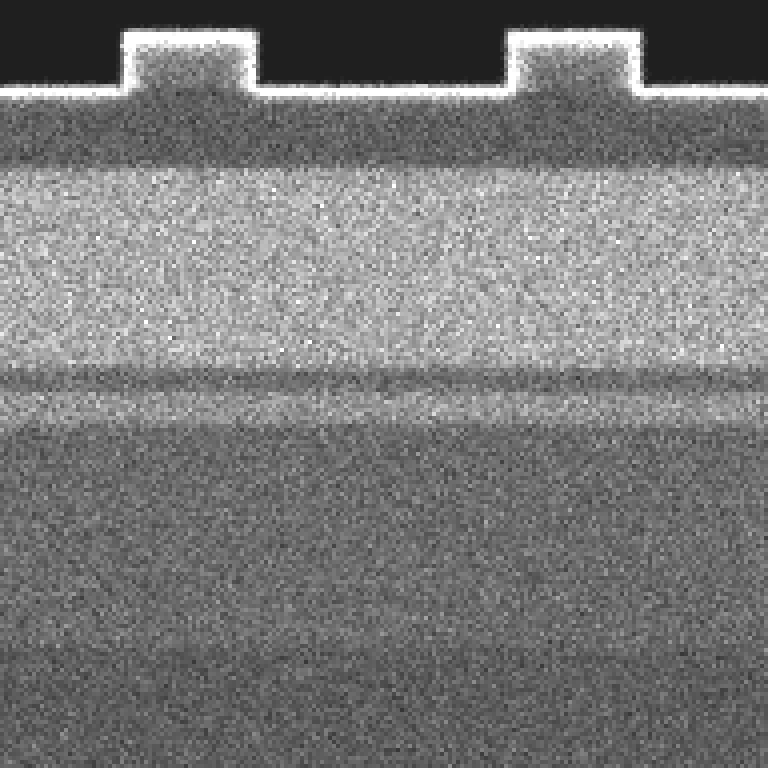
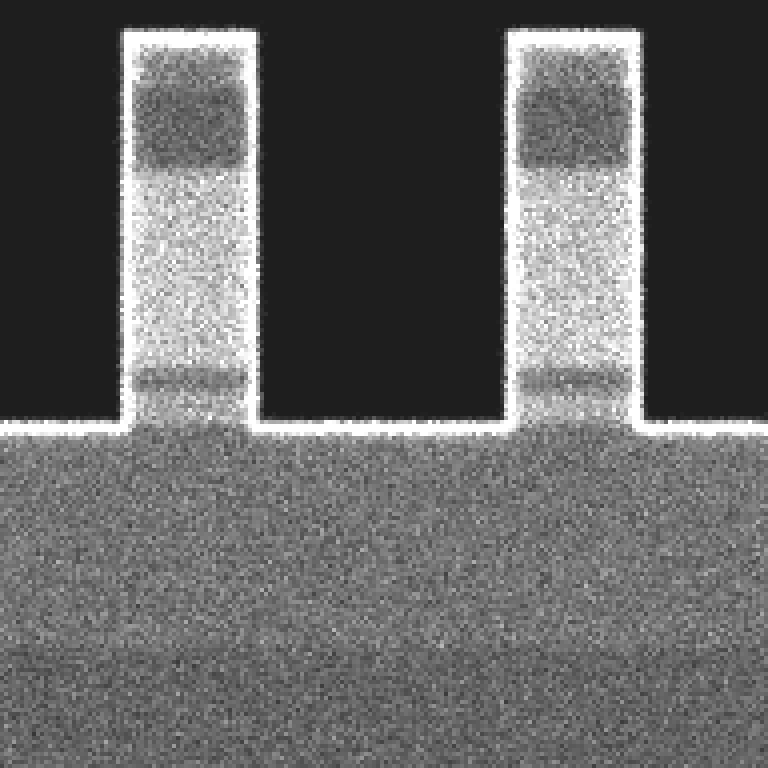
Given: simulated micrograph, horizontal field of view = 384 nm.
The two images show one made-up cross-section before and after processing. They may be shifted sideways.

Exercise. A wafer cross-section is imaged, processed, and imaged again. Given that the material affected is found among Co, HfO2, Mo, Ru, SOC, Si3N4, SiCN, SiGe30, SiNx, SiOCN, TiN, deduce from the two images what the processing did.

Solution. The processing removed Co and Ru and SiNx and TiN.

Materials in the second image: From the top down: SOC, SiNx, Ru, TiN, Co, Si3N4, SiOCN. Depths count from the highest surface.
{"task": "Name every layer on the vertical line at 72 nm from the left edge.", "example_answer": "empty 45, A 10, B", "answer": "SOC 28, SiNx 40, Ru 100, TiN 12, Co 16, Si3N4 112, SiOCN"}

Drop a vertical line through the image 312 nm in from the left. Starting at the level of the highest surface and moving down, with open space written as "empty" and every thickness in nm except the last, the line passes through SOC 28, SiNx 40, Ru 100, TiN 12, Co 16, Si3N4 112, SiOCN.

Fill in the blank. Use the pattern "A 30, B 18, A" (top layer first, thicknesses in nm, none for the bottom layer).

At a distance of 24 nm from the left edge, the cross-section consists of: empty 196, Si3N4 112, SiOCN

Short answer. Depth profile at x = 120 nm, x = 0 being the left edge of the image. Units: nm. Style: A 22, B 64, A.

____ SOC 28, SiNx 40, Ru 100, TiN 12, Co 16, Si3N4 112, SiOCN